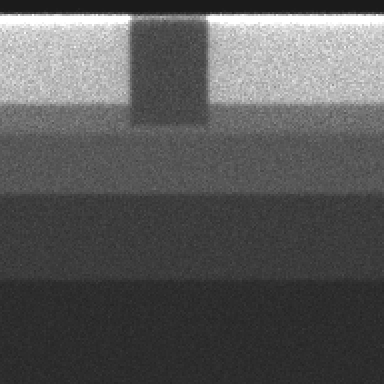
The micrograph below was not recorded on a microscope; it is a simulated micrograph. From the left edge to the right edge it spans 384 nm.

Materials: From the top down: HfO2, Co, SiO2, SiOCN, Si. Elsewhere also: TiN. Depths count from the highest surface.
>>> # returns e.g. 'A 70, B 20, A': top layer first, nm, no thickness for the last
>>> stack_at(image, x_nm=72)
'HfO2 88, Co 30, SiO2 60, SiOCN 86, Si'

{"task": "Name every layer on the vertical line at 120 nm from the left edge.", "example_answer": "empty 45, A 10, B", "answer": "HfO2 88, Co 30, SiO2 60, SiOCN 86, Si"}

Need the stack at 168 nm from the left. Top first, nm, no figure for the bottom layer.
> TiN 110, Co 8, SiO2 60, SiOCN 86, Si